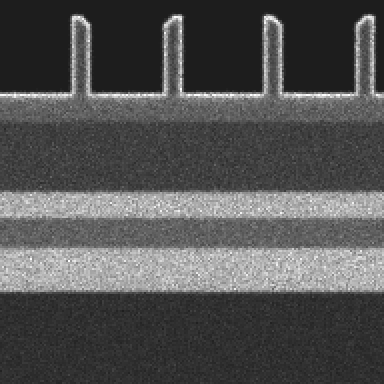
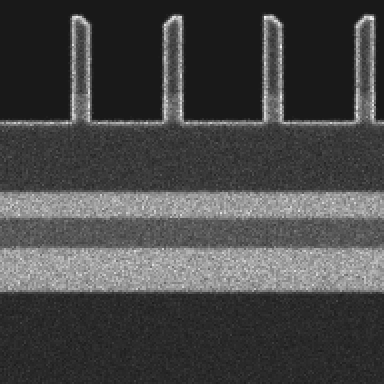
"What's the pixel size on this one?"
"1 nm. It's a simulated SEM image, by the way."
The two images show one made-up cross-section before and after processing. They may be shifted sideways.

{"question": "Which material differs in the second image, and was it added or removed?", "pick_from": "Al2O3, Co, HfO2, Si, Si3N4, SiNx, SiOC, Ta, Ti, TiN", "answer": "Co, removed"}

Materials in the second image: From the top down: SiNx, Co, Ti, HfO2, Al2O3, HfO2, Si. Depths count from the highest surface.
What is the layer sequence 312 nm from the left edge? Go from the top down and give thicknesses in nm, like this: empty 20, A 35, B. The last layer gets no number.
empty 106, Ti 70, HfO2 26, Al2O3 30, HfO2 44, Si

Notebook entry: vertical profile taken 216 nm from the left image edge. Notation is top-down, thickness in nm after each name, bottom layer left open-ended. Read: empty 106, Ti 70, HfO2 26, Al2O3 30, HfO2 44, Si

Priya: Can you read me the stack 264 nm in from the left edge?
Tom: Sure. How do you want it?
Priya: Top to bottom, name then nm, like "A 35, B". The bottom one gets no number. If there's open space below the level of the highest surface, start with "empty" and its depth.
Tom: SiNx 78, Co 28, Ti 70, HfO2 26, Al2O3 30, HfO2 44, Si